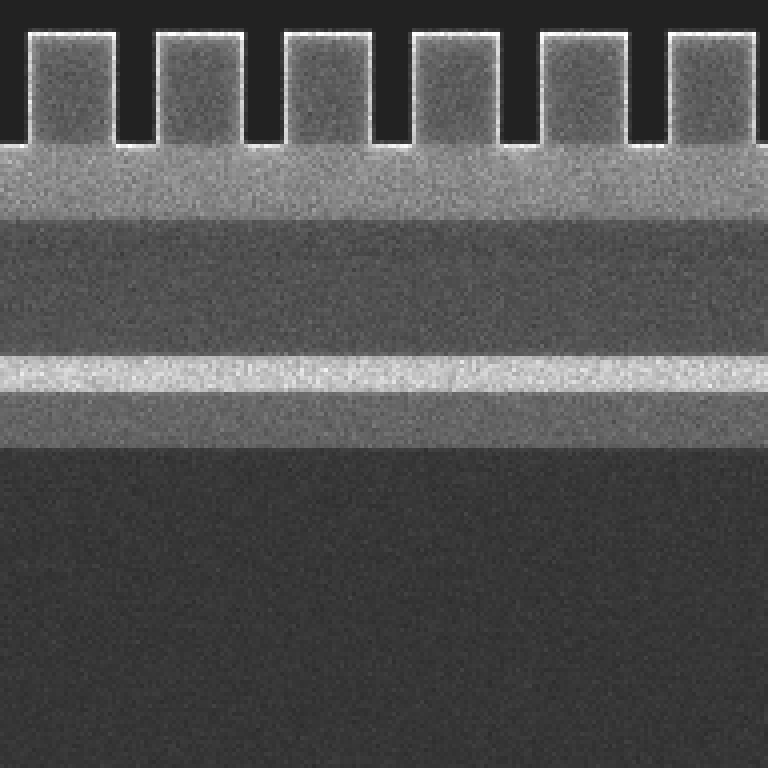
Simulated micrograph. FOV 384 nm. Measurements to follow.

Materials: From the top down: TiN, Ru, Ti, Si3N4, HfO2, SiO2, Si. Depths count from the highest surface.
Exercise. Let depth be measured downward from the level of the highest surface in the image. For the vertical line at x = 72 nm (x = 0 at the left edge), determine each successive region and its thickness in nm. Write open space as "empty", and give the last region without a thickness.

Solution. empty 56, Ru 38, Ti 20, Si3N4 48, HfO2 18, SiO2 28, Si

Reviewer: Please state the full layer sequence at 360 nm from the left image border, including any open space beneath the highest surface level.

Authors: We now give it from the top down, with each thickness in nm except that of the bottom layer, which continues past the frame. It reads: TiN 56, Ru 38, Ti 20, Si3N4 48, HfO2 18, SiO2 28, Si